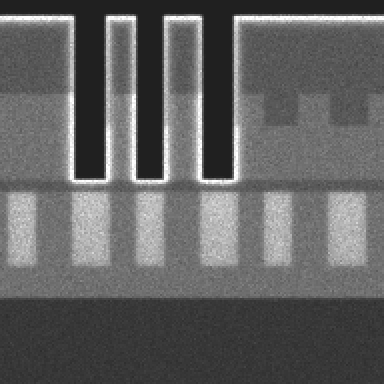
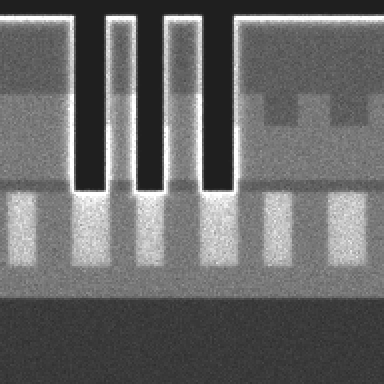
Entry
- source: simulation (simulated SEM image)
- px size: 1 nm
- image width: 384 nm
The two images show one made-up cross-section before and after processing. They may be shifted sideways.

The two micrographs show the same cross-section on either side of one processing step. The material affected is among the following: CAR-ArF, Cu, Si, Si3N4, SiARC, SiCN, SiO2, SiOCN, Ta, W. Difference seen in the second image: Si3N4 removed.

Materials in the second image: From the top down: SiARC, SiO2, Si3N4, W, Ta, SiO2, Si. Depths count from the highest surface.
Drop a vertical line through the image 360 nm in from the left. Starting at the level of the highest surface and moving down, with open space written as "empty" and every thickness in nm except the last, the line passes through SiARC 110, SiO2 54, Si3N4 12, Ta 74, SiO2 32, Si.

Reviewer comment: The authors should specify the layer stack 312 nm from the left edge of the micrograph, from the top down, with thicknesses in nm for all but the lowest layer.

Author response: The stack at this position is SiARC 78, SiO2 86, Si3N4 12, SiO2 106, Si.